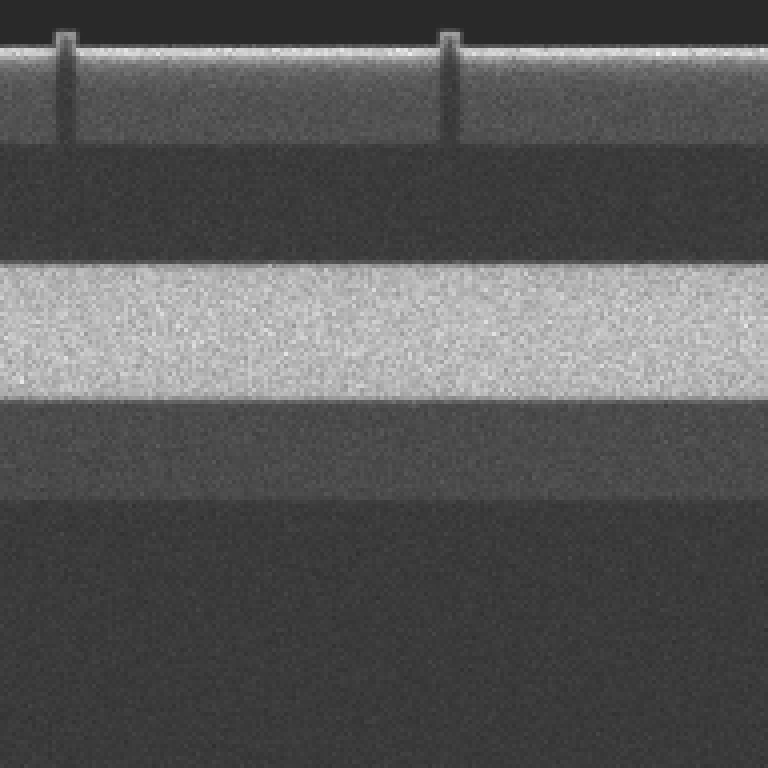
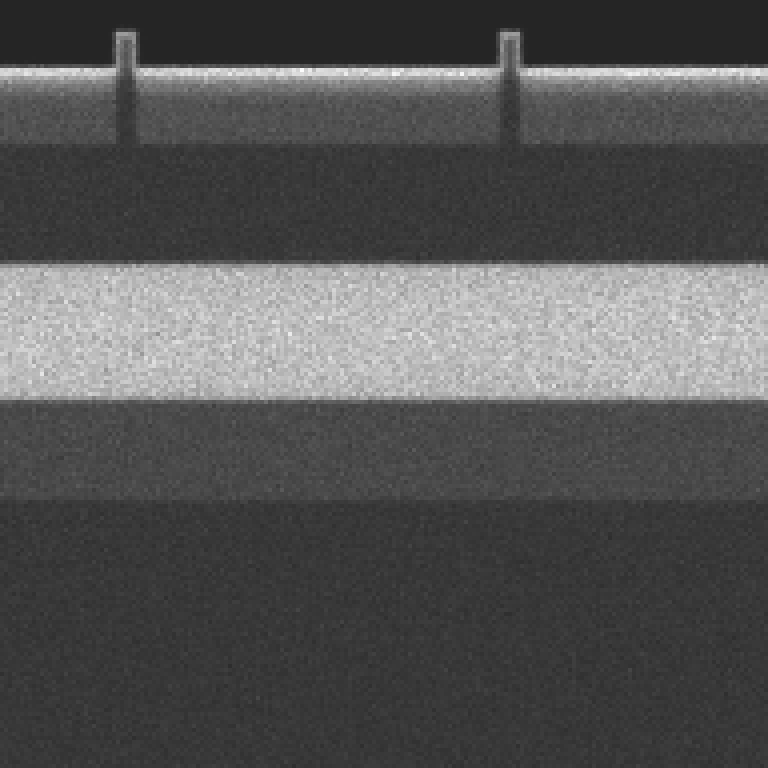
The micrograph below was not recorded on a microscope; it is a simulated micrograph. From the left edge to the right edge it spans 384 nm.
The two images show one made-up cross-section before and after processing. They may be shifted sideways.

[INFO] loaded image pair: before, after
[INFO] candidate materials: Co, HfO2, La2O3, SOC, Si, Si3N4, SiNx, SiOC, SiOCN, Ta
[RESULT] removed SOC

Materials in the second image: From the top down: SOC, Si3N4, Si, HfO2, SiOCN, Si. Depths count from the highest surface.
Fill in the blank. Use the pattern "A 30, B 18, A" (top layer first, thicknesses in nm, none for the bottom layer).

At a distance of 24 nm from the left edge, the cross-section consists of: empty 18, SOC 10, Si3N4 28, Si 60, HfO2 68, SiOCN 50, Si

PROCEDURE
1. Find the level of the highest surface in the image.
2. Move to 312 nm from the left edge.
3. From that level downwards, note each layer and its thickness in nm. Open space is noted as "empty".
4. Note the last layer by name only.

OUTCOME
empty 18, SOC 10, Si3N4 28, Si 60, HfO2 68, SiOCN 50, Si